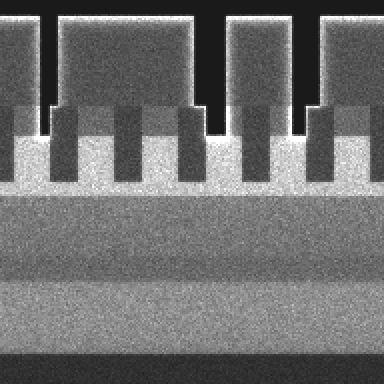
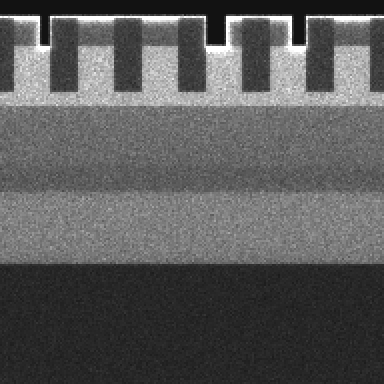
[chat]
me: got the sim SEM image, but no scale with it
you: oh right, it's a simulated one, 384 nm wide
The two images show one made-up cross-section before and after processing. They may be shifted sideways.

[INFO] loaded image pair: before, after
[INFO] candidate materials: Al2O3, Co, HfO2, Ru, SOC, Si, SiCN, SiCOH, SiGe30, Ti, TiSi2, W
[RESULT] removed SOC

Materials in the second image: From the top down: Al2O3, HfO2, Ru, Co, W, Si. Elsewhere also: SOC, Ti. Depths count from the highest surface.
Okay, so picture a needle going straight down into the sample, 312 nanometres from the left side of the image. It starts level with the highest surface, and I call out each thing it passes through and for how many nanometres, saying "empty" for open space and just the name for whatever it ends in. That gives Ti 76, HfO2 14, Ru 60, Co 26, W 72, Si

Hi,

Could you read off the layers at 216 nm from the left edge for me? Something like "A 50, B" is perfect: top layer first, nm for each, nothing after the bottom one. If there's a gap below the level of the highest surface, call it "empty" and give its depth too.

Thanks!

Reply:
empty 30, HfO2 60, Ru 60, Co 26, W 72, Si